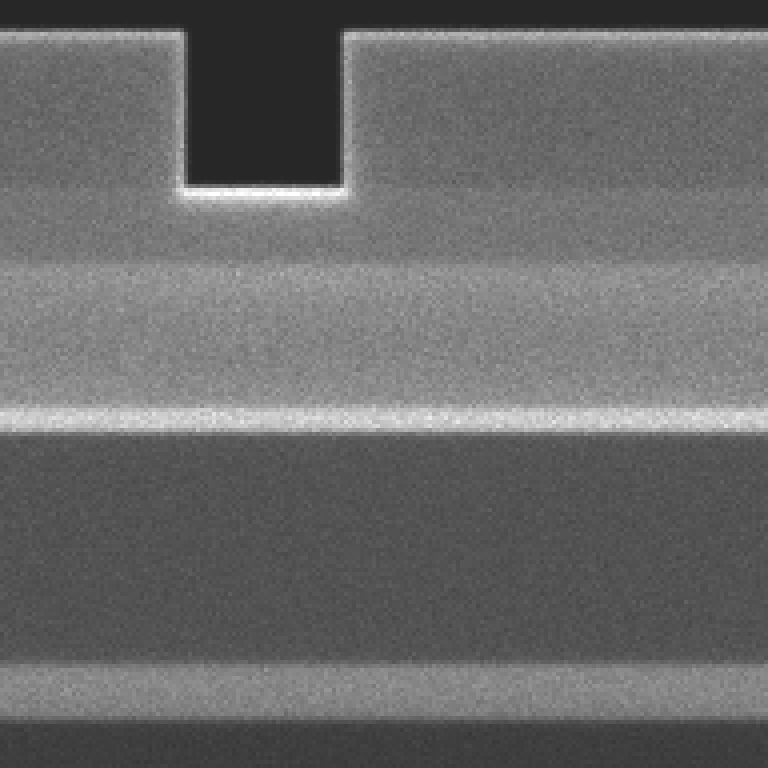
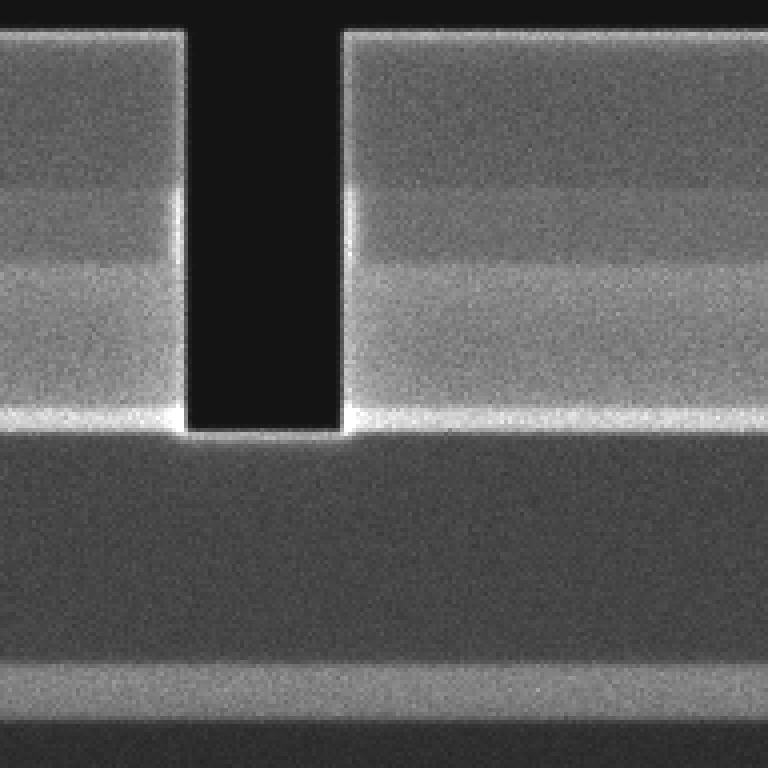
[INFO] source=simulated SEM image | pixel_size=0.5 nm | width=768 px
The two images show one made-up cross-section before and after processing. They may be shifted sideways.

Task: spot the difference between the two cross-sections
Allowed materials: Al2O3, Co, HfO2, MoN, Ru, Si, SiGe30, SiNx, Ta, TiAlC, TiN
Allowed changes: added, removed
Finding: removed Al2O3 and Co and HfO2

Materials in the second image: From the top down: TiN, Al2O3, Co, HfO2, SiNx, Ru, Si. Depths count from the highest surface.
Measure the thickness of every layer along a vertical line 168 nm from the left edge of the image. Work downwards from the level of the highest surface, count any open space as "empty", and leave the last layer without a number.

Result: empty 200, SiNx 116, Ru 28, Si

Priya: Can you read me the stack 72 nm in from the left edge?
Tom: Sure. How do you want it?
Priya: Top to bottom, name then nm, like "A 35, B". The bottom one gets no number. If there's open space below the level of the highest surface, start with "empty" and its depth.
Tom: TiN 78, Al2O3 38, Co 72, HfO2 12, SiNx 116, Ru 28, Si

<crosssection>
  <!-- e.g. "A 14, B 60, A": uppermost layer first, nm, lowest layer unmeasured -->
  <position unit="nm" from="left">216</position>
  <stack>TiN 78, Al2O3 38, Co 72, HfO2 12, SiNx 116, Ru 28, Si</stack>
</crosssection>